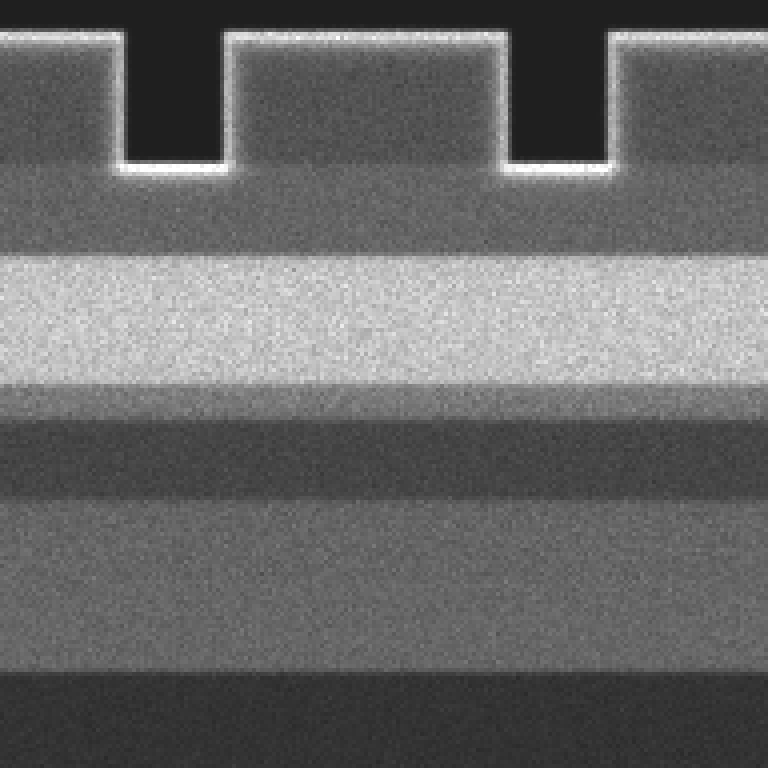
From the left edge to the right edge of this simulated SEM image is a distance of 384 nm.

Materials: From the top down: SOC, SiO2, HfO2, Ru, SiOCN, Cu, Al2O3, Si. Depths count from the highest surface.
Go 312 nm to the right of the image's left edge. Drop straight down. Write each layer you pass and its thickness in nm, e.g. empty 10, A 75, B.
SOC 66, SiO2 46, HfO2 64, Ru 18, SiOCN 40, Cu 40, Al2O3 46, Si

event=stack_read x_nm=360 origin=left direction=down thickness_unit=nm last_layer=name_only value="SOC 66, SiO2 46, HfO2 64, Ru 18, SiOCN 40, Cu 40, Al2O3 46, Si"